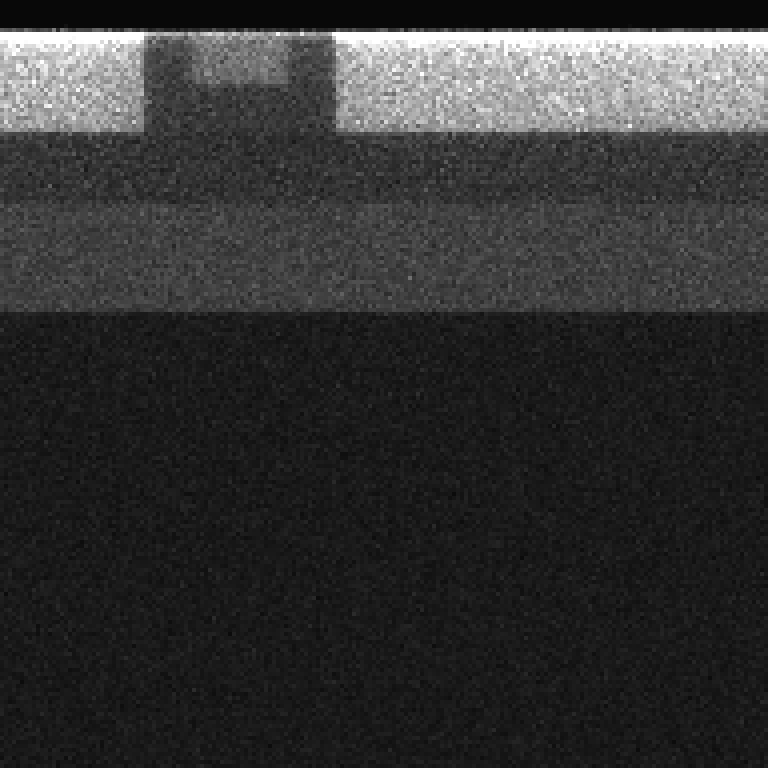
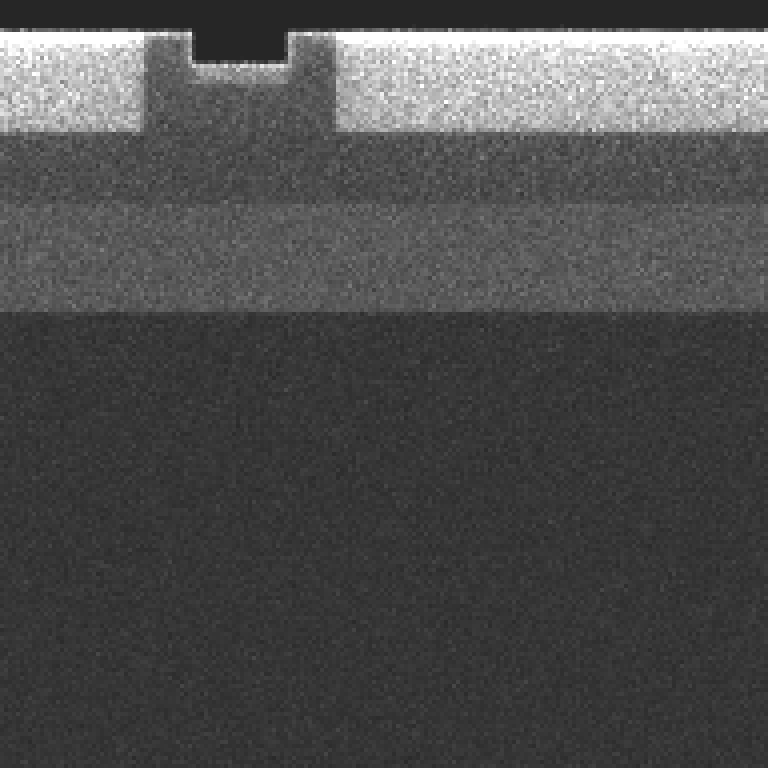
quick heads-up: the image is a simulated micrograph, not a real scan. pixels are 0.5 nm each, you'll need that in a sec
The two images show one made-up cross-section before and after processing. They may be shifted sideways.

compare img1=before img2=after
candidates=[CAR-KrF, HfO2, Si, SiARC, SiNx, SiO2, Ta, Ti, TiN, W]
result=removed:W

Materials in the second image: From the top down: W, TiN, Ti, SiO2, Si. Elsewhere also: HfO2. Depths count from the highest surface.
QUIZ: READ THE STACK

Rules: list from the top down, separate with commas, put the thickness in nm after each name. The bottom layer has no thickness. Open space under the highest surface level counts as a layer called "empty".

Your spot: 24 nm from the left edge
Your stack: HfO2 50, Ti 36, SiO2 54, Si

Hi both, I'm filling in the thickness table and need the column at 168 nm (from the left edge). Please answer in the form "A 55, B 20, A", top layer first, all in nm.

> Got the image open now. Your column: HfO2 50, Ti 36, SiO2 54, Si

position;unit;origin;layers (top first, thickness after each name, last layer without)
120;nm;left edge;empty 16, W 10, TiN 24, Ti 36, SiO2 54, Si